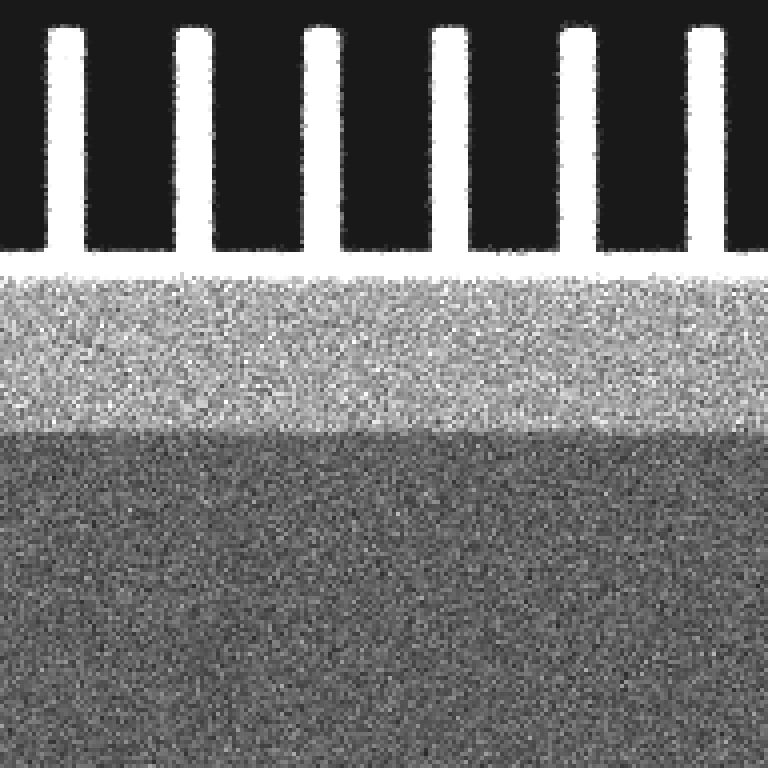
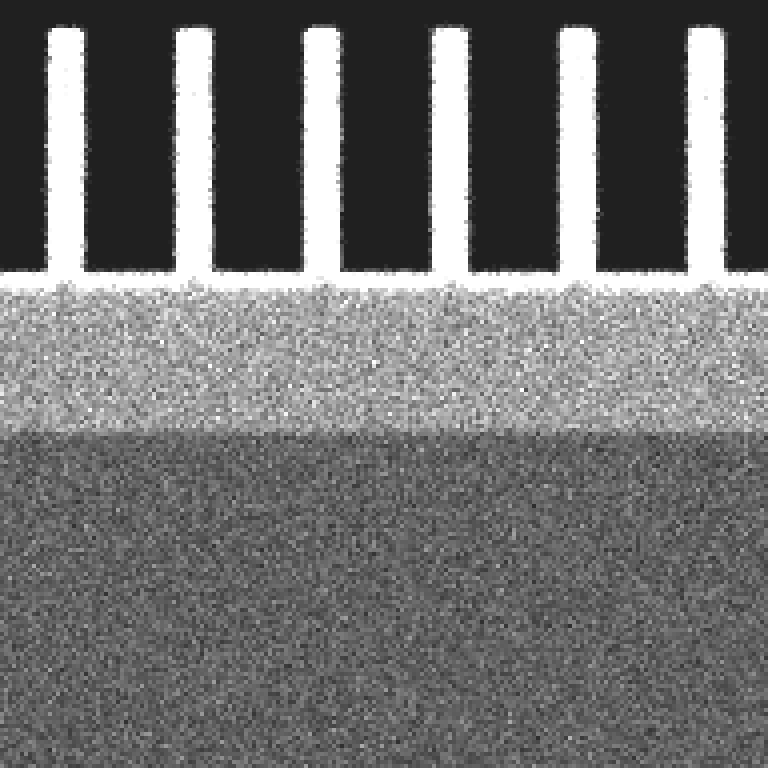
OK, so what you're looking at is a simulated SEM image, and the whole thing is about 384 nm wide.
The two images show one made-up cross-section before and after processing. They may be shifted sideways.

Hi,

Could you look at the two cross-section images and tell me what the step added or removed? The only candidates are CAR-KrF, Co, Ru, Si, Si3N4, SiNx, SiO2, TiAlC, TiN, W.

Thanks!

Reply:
removed Ru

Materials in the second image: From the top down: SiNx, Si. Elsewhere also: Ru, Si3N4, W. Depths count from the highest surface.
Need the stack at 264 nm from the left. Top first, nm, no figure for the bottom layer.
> empty 122, SiNx 78, Si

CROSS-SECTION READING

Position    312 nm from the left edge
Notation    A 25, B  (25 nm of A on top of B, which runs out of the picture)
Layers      empty 122, SiNx 78, Si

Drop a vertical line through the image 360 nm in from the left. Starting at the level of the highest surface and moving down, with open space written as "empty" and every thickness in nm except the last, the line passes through empty 122, SiNx 78, Si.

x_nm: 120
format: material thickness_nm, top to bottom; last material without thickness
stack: empty 122, SiNx 78, Si